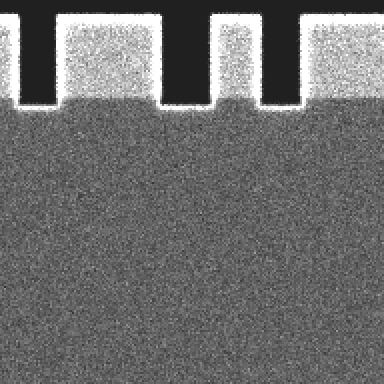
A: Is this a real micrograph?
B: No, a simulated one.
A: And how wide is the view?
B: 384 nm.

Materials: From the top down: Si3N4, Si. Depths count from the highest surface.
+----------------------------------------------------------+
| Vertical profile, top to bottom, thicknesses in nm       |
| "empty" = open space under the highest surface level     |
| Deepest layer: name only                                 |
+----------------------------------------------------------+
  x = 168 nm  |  empty 90, Si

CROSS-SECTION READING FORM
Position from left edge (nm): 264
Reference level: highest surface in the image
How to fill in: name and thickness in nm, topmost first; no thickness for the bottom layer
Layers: empty 90, Si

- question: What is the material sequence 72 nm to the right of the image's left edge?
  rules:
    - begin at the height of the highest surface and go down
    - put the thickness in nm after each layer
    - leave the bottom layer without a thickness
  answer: Si3N4 82, Si